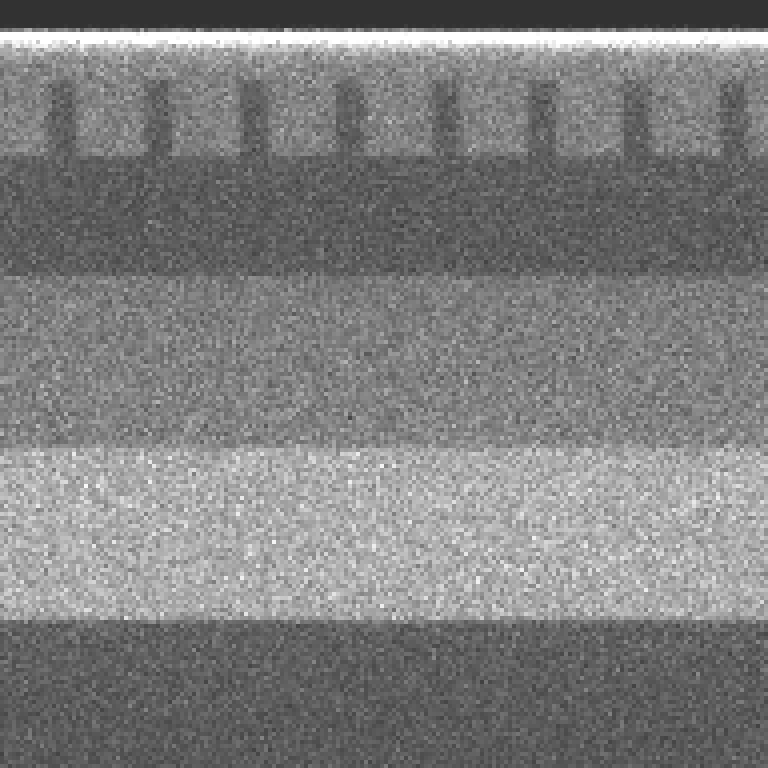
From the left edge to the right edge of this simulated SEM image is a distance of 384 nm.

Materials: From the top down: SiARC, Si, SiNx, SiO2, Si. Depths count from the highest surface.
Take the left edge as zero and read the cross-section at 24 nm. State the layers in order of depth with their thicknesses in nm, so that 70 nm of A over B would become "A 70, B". SiARC 24, Si 98, SiNx 86, SiO2 86, Si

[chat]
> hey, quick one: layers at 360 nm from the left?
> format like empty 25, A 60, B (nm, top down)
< SiARC 24, Si 98, SiNx 86, SiO2 86, Si